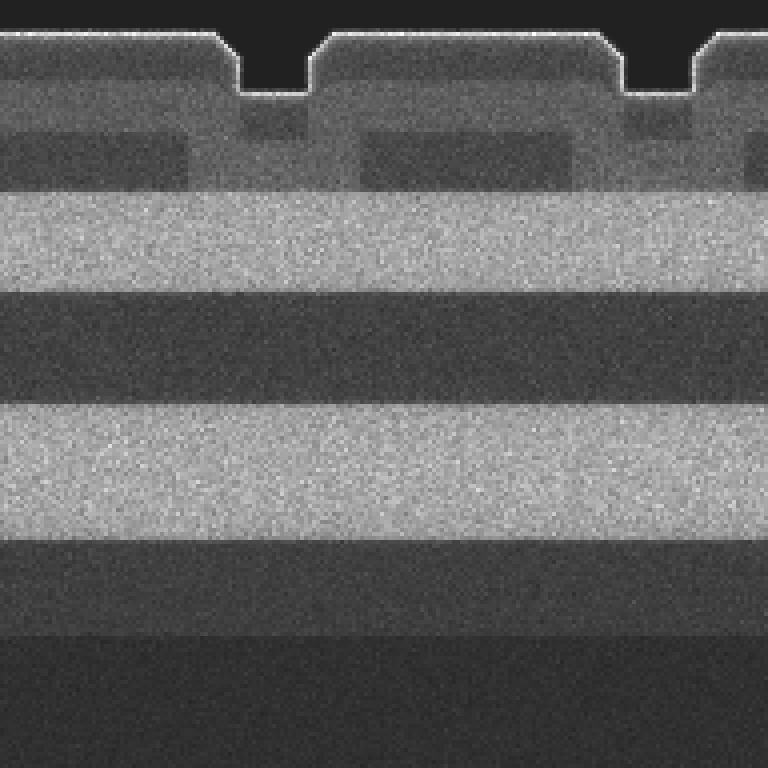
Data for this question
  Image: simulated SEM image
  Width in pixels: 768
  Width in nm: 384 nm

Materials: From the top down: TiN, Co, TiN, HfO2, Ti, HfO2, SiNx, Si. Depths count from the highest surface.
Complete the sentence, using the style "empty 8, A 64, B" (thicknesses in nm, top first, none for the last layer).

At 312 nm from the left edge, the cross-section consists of empty 30, TiN 24, Co 26, HfO2 50, Ti 56, HfO2 68, SiNx 48, Si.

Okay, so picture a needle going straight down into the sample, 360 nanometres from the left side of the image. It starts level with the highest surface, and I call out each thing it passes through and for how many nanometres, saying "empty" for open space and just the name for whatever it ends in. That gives TiN 24, Co 56, HfO2 50, Ti 56, HfO2 68, SiNx 48, Si